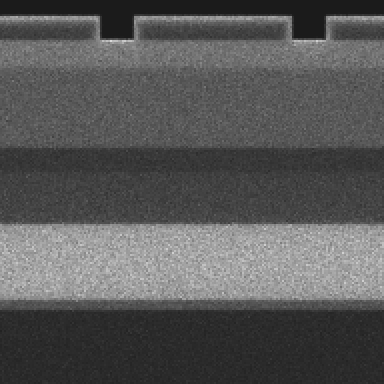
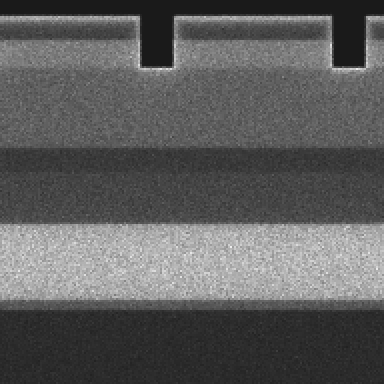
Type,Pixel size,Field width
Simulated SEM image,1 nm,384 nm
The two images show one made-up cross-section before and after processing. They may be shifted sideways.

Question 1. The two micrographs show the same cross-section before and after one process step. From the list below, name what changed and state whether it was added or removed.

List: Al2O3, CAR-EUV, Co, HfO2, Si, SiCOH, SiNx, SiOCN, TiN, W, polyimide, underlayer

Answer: W, removed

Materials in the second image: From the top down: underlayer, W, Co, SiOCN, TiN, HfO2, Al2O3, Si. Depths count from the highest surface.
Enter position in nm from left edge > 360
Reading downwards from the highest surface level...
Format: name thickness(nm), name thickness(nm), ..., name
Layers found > empty 52, Co 80, SiOCN 24, TiN 52, HfO2 76, Al2O3 10, Si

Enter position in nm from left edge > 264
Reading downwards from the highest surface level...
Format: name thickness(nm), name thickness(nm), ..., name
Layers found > underlayer 24, W 28, Co 80, SiOCN 24, TiN 52, HfO2 76, Al2O3 10, Si